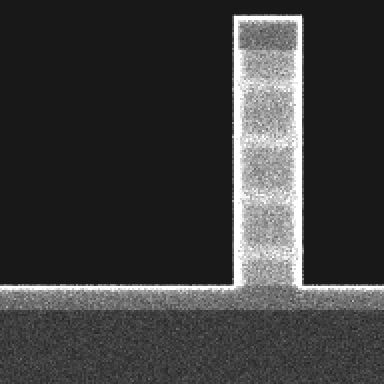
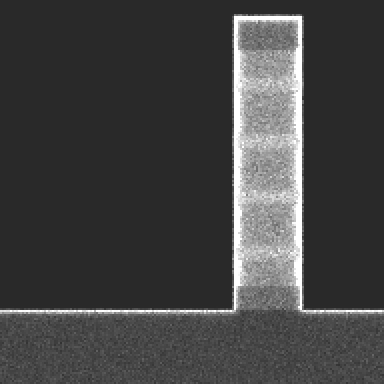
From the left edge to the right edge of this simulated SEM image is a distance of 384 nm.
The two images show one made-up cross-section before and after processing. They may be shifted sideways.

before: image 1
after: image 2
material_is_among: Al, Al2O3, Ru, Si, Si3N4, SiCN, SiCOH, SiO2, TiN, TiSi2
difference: TiN, removed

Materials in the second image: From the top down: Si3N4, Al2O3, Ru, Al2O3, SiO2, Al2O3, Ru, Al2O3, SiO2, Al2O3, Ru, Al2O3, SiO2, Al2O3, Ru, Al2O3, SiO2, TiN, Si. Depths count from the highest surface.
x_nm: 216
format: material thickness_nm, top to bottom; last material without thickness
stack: empty 294, Si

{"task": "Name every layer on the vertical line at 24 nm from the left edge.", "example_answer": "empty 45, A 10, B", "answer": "empty 294, Si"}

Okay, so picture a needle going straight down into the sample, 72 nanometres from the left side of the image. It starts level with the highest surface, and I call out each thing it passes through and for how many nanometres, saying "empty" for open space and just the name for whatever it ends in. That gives empty 294, Si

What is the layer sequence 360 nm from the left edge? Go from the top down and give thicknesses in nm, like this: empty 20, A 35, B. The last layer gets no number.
empty 294, Si